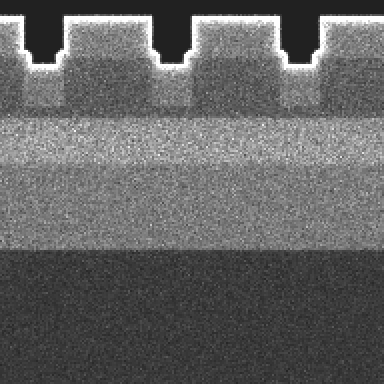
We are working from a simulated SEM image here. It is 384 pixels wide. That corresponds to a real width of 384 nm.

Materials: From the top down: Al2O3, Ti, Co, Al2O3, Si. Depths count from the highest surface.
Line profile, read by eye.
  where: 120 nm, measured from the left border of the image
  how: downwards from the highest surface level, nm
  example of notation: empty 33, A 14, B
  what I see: Al2O3 42, Ti 60, Co 46, Al2O3 86, Si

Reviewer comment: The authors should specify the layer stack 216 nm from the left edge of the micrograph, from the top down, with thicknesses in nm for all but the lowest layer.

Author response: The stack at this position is Al2O3 42, Ti 60, Co 46, Al2O3 86, Si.